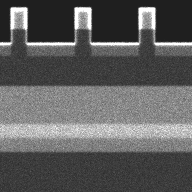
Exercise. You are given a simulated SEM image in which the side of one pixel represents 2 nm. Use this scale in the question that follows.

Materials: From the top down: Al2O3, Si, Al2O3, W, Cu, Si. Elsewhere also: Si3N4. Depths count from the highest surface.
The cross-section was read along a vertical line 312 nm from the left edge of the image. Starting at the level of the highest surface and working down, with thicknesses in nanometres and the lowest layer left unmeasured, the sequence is empty 70, Si3N4 26, Si 60, Al2O3 76, W 28, Cu 28, Si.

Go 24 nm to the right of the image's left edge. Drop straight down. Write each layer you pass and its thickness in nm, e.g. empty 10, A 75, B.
Al2O3 42, Si 114, Al2O3 76, W 28, Cu 28, Si